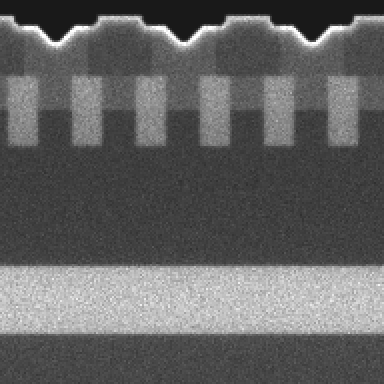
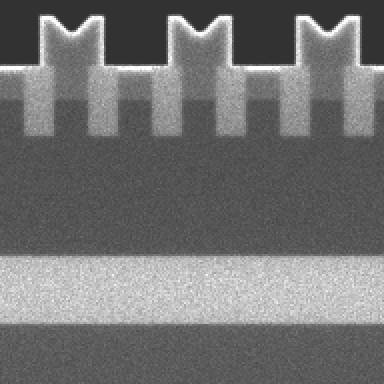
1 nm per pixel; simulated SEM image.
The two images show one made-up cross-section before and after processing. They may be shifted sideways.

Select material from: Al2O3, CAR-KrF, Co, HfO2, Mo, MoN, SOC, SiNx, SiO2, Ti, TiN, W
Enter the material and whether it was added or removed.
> SOC / removed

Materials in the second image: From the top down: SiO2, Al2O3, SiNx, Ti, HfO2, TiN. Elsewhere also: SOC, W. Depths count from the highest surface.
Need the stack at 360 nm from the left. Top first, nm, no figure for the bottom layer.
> empty 50, W 70, SiNx 36, Ti 84, HfO2 68, TiN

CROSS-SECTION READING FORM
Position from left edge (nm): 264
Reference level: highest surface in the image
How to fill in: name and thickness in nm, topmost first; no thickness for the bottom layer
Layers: empty 50, Al2O3 34, SiNx 72, Ti 84, HfO2 68, TiN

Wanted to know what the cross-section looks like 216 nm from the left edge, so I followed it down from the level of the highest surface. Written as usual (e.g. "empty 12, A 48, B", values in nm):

empty 2, SiO2 48, W 70, SiNx 36, Ti 84, HfO2 68, TiN